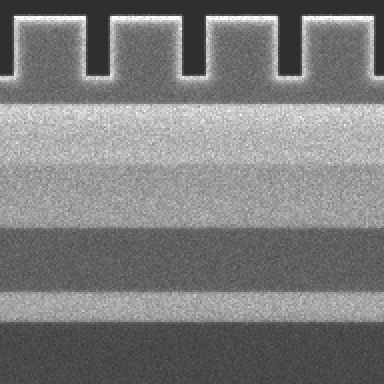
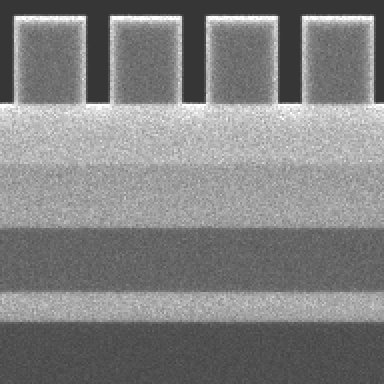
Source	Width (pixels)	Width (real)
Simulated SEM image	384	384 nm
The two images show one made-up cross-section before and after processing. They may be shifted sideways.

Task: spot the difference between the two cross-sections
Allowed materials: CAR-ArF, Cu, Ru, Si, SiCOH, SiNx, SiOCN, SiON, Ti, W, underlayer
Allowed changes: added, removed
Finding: removed underlayer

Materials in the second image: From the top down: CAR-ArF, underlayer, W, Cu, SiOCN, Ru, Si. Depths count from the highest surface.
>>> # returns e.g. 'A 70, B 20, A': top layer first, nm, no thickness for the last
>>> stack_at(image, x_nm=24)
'CAR-ArF 60, underlayer 28, W 60, Cu 64, SiOCN 64, Ru 30, Si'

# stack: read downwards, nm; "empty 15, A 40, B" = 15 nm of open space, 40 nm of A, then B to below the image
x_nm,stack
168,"CAR-ArF 60, underlayer 28, W 60, Cu 64, SiOCN 64, Ru 30, Si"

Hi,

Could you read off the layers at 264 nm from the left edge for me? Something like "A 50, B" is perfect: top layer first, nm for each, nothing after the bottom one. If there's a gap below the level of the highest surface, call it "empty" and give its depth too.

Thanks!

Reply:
CAR-ArF 60, underlayer 28, W 60, Cu 64, SiOCN 64, Ru 30, Si